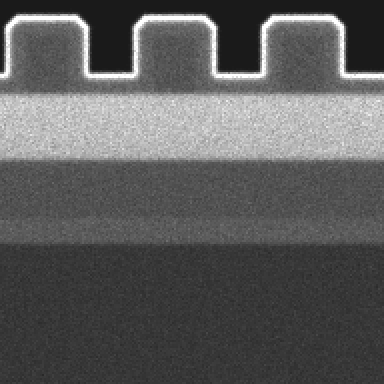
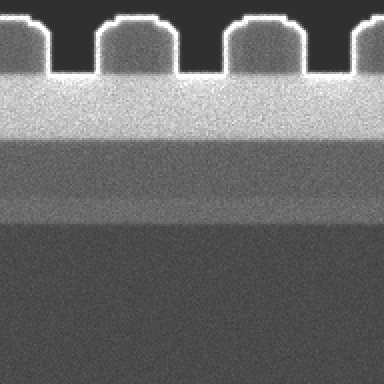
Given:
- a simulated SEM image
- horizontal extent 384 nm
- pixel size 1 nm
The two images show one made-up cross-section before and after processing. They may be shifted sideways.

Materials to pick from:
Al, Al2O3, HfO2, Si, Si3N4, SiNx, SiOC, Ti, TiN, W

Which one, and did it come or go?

Si3N4 - removed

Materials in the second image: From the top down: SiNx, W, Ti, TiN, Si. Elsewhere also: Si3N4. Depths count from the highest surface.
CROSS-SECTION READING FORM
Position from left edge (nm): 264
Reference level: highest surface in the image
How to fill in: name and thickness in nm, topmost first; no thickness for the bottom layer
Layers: SiNx 58, W 66, Ti 58, TiN 26, Si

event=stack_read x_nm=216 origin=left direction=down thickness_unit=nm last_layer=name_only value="empty 58, W 66, Ti 58, TiN 26, Si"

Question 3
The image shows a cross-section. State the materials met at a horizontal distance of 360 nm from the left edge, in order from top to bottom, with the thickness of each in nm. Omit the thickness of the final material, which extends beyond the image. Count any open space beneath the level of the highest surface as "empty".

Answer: empty 8, Si3N4 50, W 66, Ti 58, TiN 26, Si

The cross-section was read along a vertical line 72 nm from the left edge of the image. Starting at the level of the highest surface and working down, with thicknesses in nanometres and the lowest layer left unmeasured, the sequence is empty 58, W 66, Ti 58, TiN 26, Si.